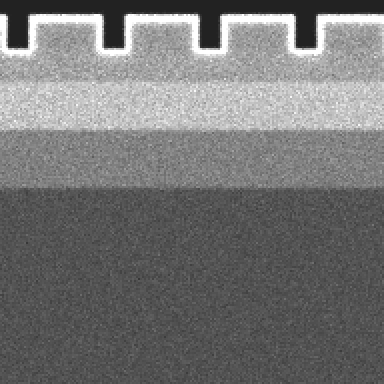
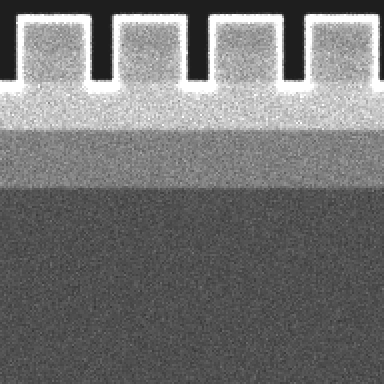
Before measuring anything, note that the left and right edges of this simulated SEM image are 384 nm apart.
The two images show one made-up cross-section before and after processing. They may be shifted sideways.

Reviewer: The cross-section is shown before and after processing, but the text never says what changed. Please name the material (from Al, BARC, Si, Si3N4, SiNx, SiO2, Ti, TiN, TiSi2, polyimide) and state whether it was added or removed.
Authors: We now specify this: TiN, removed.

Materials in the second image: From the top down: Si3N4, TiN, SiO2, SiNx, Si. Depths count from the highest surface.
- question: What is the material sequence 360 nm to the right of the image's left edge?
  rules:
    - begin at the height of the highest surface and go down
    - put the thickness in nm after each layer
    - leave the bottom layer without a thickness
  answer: Si3N4 34, TiN 32, SiO2 48, SiNx 58, Si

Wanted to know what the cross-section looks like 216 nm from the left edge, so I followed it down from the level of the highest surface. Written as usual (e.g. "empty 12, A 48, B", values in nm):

Si3N4 34, TiN 32, SiO2 48, SiNx 58, Si